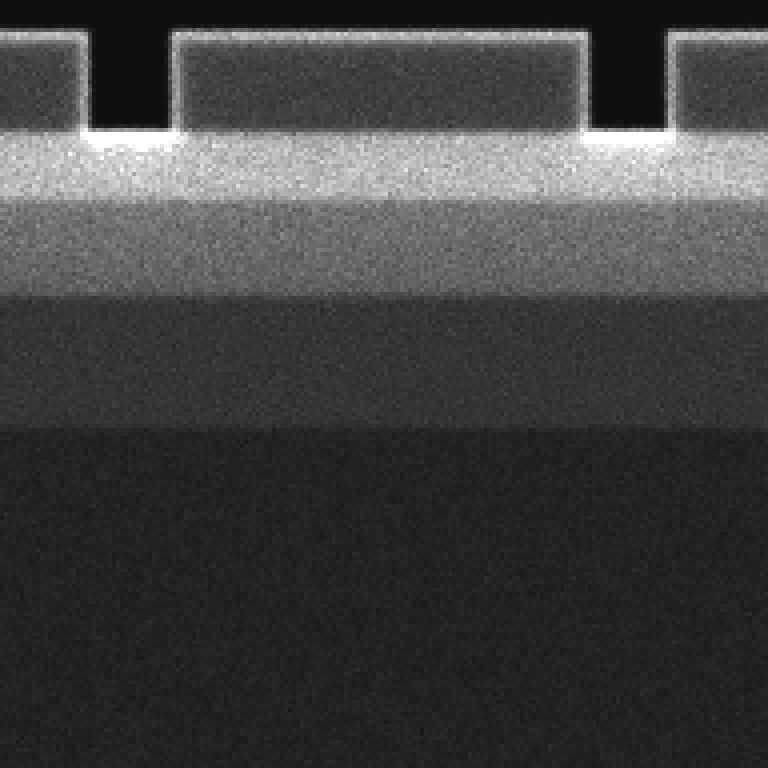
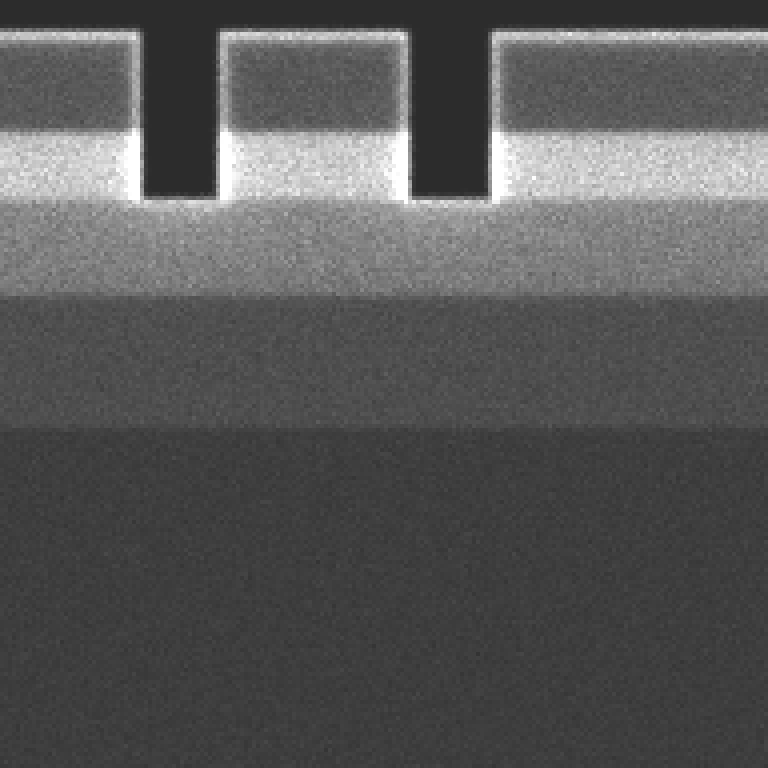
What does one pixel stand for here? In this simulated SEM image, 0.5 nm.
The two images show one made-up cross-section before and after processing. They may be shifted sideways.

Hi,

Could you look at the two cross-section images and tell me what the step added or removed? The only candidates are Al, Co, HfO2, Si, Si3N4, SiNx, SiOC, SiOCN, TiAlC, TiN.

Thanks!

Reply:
removed HfO2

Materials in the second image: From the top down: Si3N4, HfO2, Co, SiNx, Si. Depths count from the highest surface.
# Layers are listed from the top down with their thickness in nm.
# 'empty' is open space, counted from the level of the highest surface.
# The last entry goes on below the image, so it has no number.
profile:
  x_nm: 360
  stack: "Si3N4 50, HfO2 34, Co 48, SiNx 66, Si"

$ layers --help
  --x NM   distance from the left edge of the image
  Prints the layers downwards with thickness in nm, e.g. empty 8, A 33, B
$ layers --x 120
Si3N4 50, HfO2 34, Co 48, SiNx 66, Si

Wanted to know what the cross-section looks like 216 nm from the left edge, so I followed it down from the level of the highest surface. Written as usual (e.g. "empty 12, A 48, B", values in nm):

empty 84, Co 48, SiNx 66, Si